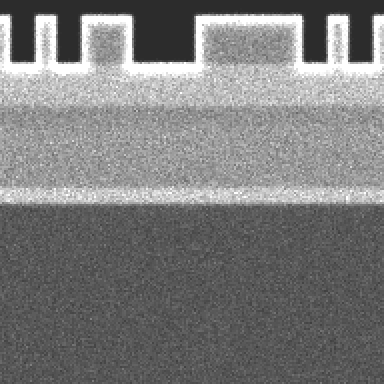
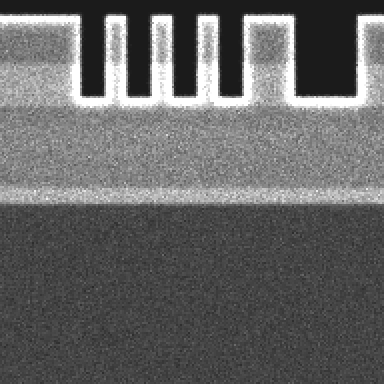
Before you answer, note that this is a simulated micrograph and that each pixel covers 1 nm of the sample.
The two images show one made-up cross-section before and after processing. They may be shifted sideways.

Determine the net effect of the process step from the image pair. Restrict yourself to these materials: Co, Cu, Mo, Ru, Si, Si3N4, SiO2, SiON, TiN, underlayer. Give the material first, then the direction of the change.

SiO2: removed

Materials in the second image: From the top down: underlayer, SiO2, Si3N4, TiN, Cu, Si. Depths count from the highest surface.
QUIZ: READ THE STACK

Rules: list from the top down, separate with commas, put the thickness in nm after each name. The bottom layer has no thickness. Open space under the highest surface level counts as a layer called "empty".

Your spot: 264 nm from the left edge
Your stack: underlayer 48, SiO2 42, Si3N4 20, TiN 62, Cu 16, Si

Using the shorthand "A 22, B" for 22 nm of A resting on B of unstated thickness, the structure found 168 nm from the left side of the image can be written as underlayer 48, SiO2 42, Si3N4 20, TiN 62, Cu 16, Si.